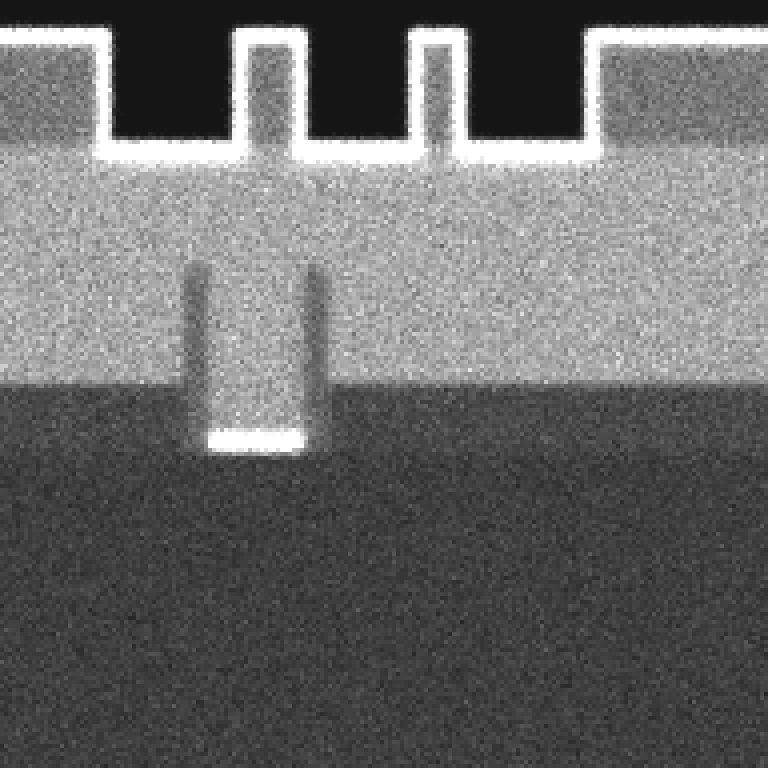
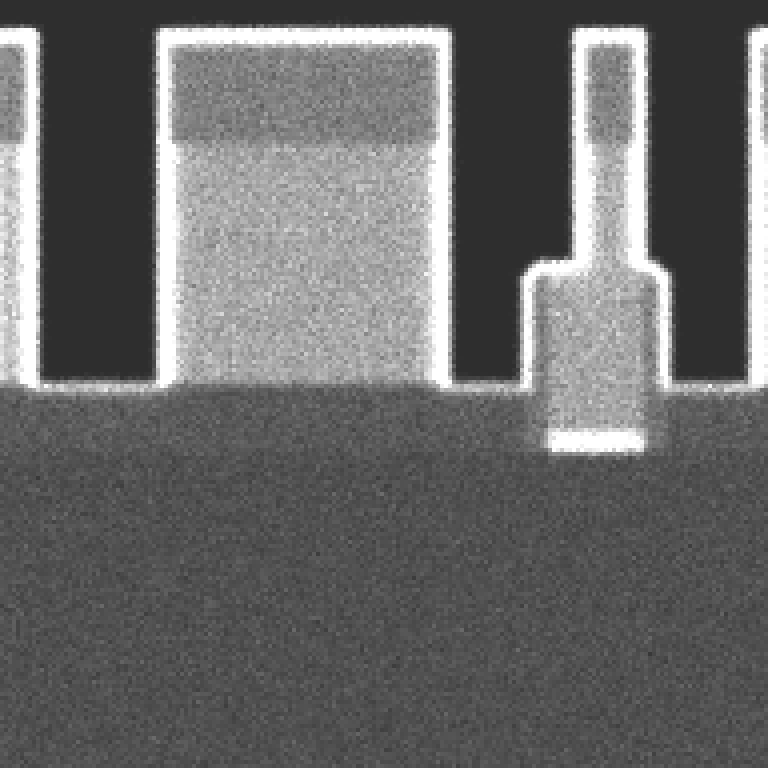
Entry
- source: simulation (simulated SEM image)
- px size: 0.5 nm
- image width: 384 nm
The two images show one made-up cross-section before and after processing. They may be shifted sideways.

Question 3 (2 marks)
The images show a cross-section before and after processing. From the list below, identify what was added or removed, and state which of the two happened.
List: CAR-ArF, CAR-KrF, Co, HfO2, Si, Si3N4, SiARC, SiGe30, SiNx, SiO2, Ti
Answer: SiO2 was removed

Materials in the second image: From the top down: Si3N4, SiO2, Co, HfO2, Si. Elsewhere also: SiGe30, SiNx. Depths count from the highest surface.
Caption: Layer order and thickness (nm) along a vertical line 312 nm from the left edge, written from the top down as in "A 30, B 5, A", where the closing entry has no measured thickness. Si3N4 56, SiO2 60, Co 84, HfO2 10, Si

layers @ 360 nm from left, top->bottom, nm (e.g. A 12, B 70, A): empty 176, SiGe30 34, Si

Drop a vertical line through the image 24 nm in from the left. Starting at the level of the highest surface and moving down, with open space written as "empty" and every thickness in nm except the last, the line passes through empty 176, SiGe30 34, Si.